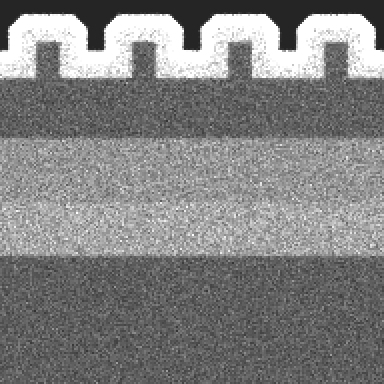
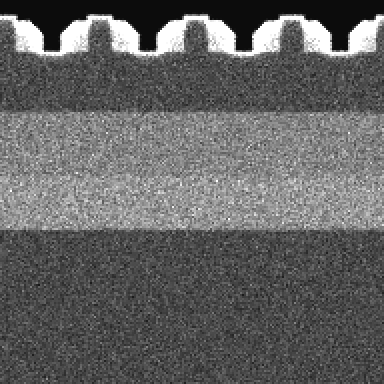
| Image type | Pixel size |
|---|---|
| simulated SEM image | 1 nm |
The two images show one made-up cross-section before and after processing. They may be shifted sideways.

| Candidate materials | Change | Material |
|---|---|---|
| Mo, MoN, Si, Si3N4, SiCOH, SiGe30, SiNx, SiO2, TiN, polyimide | removed | SiO2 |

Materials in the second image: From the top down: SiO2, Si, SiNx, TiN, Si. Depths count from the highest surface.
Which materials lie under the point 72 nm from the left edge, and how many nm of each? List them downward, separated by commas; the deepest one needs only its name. empty 8, SiO2 28, Si 60, SiNx 64, TiN 54, Si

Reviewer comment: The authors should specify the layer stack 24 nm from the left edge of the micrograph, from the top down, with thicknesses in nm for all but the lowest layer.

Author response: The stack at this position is empty 6, SiO2 30, Si 60, SiNx 64, TiN 54, Si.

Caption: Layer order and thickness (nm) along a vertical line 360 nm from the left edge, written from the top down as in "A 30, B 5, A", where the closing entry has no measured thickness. empty 8, SiO2 28, Si 60, SiNx 64, TiN 54, Si